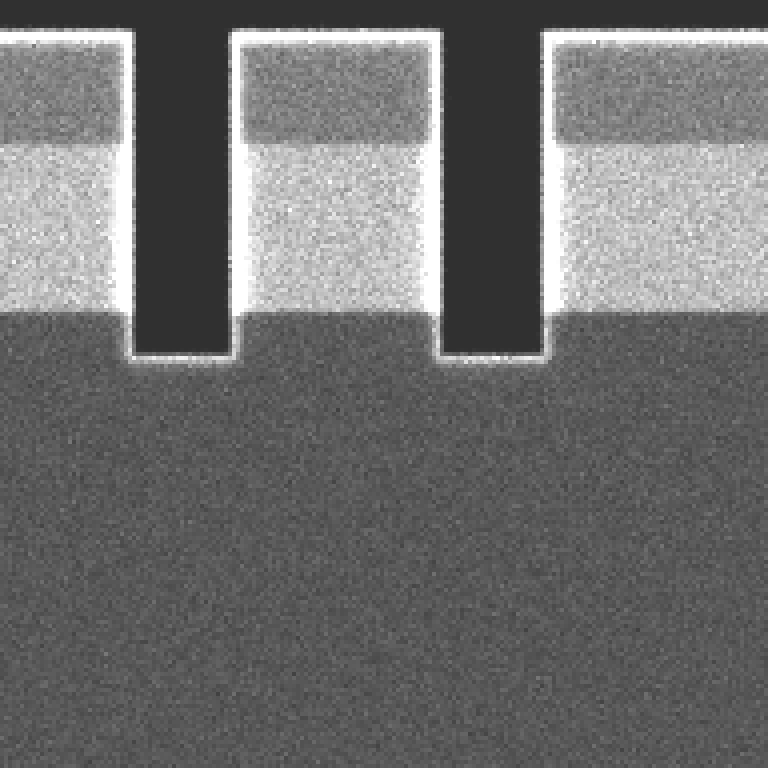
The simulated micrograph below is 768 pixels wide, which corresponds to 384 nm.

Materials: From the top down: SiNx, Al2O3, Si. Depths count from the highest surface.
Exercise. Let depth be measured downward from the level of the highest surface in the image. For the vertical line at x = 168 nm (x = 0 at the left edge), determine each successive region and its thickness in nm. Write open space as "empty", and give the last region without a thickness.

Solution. SiNx 56, Al2O3 84, Si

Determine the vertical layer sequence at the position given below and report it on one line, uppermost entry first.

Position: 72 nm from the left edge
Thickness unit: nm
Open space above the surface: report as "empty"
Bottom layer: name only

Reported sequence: empty 162, Si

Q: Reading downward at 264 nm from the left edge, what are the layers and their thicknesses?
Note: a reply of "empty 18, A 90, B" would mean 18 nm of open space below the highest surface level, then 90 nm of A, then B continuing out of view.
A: empty 162, Si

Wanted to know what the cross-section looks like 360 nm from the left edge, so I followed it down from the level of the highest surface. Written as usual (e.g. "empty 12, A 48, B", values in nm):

SiNx 56, Al2O3 84, Si